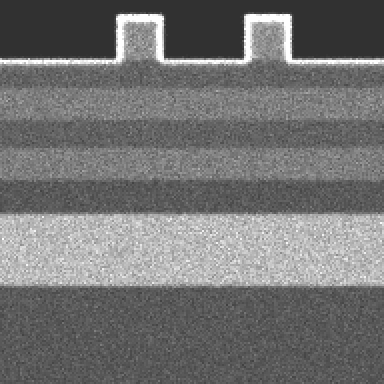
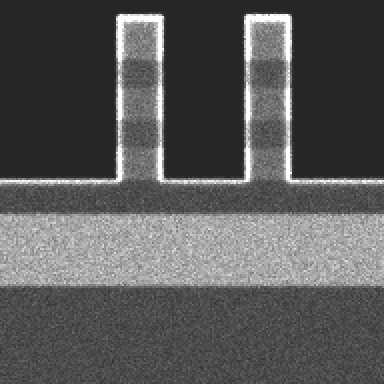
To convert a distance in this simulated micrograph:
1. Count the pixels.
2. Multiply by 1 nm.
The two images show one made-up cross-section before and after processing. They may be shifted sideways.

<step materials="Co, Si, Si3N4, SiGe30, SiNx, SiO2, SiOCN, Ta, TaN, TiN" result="removed SiGe30 and SiNx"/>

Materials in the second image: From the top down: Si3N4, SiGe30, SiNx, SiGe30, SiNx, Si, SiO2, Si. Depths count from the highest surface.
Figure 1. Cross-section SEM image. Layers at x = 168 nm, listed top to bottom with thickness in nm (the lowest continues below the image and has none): empty 164, Si 34, SiO2 72, Si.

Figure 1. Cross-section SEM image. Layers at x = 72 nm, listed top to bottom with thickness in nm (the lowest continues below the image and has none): empty 164, Si 34, SiO2 72, Si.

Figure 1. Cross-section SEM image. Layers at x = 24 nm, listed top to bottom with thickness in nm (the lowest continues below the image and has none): empty 164, Si 34, SiO2 72, Si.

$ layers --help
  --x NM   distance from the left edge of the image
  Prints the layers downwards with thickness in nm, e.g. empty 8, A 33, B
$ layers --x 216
empty 164, Si 34, SiO2 72, Si